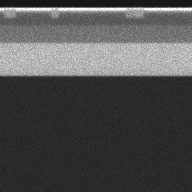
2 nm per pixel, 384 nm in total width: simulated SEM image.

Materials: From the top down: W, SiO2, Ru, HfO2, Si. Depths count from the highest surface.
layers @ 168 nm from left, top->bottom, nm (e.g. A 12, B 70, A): SiO2 34, Ru 36, HfO2 66, Si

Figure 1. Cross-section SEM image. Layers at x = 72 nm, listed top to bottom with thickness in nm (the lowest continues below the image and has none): SiO2 34, Ru 36, HfO2 66, Si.